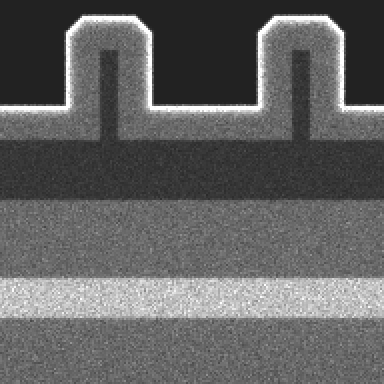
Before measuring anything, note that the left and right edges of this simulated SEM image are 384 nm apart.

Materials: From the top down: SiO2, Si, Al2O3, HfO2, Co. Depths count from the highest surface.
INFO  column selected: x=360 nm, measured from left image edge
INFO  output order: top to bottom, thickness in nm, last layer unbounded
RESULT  empty 90, SiO2 34, Si 60, Al2O3 78, HfO2 40, Co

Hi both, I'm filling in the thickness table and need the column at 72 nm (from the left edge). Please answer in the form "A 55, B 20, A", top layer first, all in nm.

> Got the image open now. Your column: empty 10, SiO2 114, Si 60, Al2O3 78, HfO2 40, Co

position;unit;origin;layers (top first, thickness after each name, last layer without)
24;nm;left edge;empty 90, SiO2 34, Si 60, Al2O3 78, HfO2 40, Co